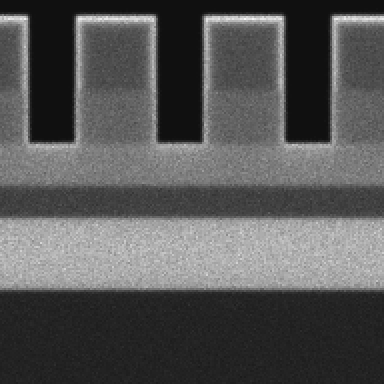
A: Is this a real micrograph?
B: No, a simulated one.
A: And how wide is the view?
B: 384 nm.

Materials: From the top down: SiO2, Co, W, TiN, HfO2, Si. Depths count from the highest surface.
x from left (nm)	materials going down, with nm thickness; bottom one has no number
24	SiO2 74, Co 54, W 42, TiN 32, HfO2 72, Si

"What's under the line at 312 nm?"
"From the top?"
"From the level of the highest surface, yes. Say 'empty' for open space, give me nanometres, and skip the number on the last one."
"empty 128, W 42, TiN 32, HfO2 72, Si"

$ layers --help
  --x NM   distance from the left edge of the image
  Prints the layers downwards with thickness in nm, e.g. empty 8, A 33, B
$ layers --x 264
SiO2 74, Co 54, W 42, TiN 32, HfO2 72, Si